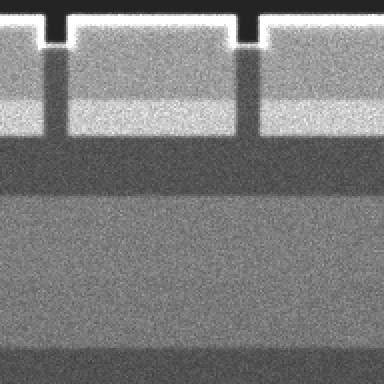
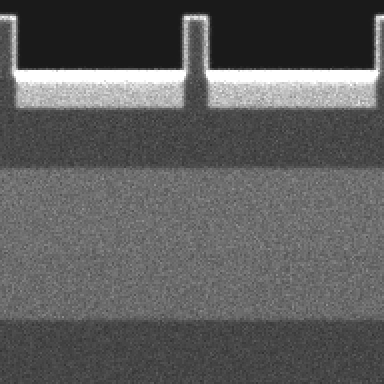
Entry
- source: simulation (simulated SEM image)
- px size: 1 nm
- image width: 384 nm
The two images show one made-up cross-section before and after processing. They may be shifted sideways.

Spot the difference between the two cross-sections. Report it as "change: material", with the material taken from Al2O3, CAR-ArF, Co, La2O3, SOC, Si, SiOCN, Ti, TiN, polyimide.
removed: SOC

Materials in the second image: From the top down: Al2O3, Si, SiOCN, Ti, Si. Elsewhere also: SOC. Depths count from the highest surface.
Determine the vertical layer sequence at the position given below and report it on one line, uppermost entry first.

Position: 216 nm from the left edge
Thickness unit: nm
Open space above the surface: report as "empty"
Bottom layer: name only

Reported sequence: empty 56, Al2O3 36, Si 60, SiOCN 84, Ti 68, Si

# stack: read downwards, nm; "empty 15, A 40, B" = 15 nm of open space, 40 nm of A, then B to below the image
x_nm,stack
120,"empty 56, Al2O3 36, Si 60, SiOCN 84, Ti 68, Si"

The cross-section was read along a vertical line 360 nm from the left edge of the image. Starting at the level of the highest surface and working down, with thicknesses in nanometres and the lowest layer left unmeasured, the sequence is empty 56, Al2O3 36, Si 60, SiOCN 84, Ti 68, Si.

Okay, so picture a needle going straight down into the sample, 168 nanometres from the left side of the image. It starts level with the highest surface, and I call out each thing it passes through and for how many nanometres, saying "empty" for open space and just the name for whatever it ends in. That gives empty 56, Al2O3 36, Si 60, SiOCN 84, Ti 68, Si